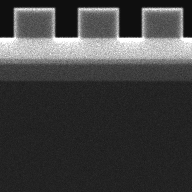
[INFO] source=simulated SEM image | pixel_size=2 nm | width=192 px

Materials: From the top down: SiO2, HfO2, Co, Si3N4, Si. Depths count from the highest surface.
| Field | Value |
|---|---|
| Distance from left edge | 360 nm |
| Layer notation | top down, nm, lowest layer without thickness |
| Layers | SiO2 60, HfO2 42, Co 10, Si3N4 34, Si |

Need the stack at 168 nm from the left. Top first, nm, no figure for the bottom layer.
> SiO2 60, HfO2 42, Co 10, Si3N4 34, Si